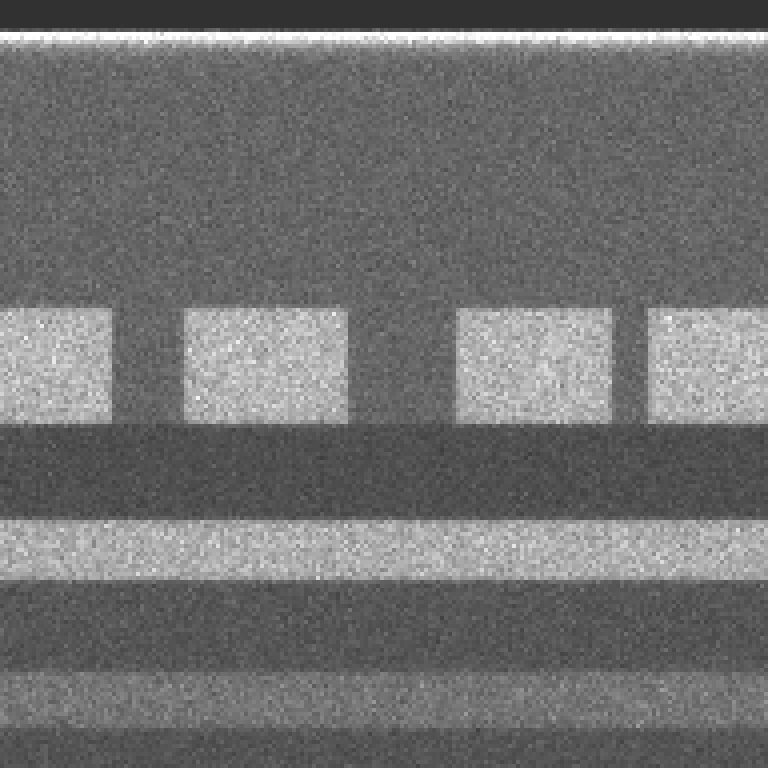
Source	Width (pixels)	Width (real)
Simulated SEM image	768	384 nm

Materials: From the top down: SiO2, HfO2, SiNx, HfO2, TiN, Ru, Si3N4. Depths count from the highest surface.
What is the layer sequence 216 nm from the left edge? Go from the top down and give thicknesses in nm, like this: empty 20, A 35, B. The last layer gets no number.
SiO2 196, SiNx 48, HfO2 30, TiN 46, Ru 28, Si3N4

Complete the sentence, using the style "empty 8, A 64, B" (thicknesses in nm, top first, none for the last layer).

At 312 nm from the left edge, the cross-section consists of SiO2 196, SiNx 48, HfO2 30, TiN 46, Ru 28, Si3N4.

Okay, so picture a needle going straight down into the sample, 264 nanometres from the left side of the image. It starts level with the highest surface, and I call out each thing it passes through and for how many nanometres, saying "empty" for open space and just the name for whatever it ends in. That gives SiO2 138, HfO2 58, SiNx 48, HfO2 30, TiN 46, Ru 28, Si3N4